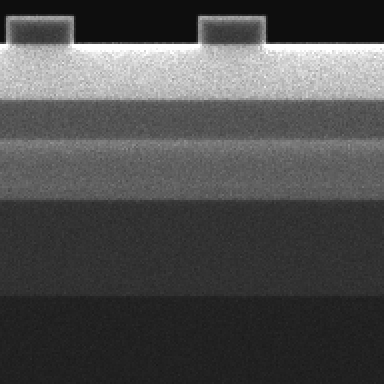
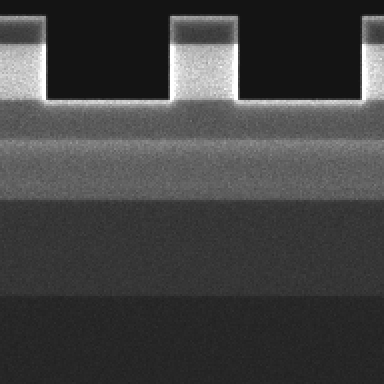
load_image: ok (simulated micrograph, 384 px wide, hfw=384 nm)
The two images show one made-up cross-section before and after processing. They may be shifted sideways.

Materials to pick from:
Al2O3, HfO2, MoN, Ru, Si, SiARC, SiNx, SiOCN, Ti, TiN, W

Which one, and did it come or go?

HfO2 - removed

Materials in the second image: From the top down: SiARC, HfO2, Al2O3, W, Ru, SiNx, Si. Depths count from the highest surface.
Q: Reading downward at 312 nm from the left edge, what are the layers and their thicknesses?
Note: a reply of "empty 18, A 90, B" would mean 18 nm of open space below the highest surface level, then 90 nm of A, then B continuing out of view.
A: empty 84, Al2O3 40, W 48, Ru 12, SiNx 96, Si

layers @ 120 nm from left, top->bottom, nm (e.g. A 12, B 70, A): empty 84, Al2O3 40, W 48, Ru 12, SiNx 96, Si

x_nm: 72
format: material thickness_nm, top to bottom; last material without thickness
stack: empty 84, Al2O3 40, W 48, Ru 12, SiNx 96, Si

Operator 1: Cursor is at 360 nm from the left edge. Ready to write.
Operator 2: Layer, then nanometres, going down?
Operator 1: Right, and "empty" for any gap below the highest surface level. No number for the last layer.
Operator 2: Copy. empty 84, Al2O3 40, W 48, Ru 12, SiNx 96, Si